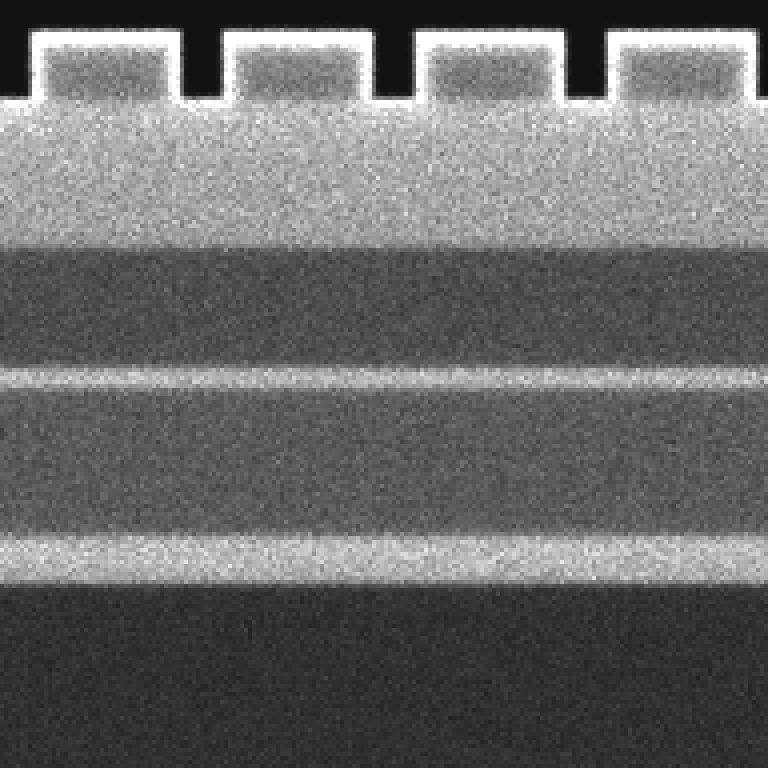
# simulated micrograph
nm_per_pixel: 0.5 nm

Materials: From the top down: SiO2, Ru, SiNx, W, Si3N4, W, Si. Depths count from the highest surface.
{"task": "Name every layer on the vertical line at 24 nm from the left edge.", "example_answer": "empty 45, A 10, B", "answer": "SiO2 34, Ru 74, SiNx 60, W 10, Si3N4 74, W 24, Si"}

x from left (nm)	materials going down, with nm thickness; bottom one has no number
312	SiO2 34, Ru 74, SiNx 60, W 10, Si3N4 74, W 24, Si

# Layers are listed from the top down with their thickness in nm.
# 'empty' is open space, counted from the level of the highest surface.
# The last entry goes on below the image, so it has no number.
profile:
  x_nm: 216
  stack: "SiO2 34, Ru 74, SiNx 60, W 10, Si3N4 74, W 24, Si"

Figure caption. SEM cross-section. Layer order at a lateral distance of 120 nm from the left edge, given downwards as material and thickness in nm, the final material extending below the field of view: SiO2 34, Ru 74, SiNx 60, W 10, Si3N4 74, W 24, Si